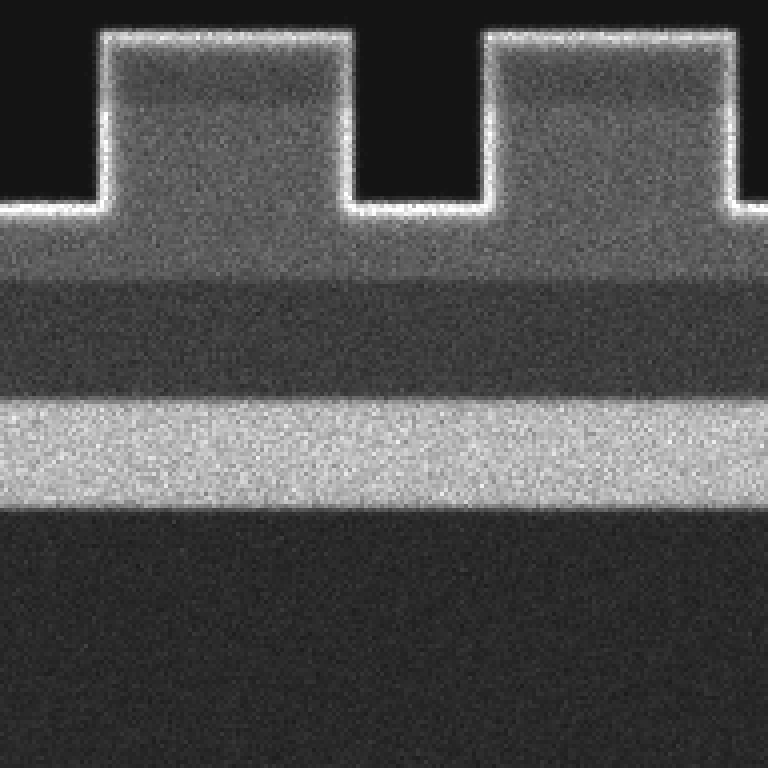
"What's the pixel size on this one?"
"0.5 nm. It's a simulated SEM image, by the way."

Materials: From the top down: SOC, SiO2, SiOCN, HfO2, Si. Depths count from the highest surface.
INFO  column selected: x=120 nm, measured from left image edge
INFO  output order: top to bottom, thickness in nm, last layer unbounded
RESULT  SOC 36, SiO2 88, SiOCN 60, HfO2 54, Si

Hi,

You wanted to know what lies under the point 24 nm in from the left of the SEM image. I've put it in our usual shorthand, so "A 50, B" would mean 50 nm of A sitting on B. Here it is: empty 86, SiO2 38, SiOCN 60, HfO2 54, Si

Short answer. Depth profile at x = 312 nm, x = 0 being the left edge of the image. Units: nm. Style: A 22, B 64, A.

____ SOC 36, SiO2 88, SiOCN 60, HfO2 54, Si